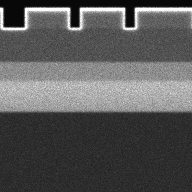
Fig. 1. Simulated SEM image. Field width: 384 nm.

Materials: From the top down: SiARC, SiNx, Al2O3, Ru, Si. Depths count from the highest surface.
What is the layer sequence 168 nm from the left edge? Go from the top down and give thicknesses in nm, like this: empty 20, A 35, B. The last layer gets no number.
SiARC 40, SiNx 68, Al2O3 38, Ru 62, Si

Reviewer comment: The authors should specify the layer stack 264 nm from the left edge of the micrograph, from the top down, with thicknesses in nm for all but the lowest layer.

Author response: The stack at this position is empty 40, SiNx 68, Al2O3 38, Ru 62, Si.